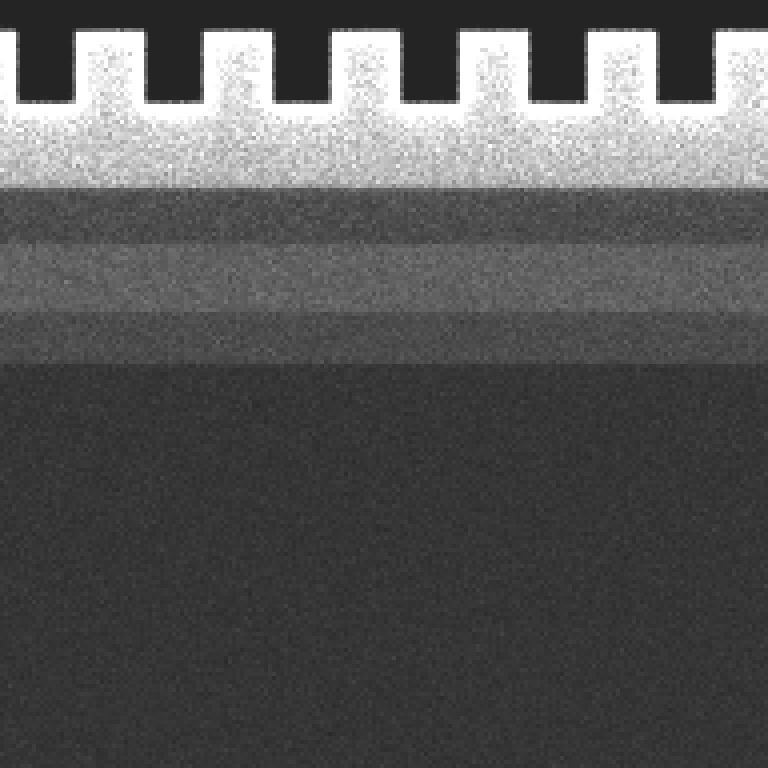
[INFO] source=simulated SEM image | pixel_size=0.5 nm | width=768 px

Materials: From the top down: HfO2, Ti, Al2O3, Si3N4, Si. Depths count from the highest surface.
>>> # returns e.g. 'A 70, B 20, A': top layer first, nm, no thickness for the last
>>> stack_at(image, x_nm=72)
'empty 36, HfO2 42, Ti 28, Al2O3 34, Si3N4 26, Si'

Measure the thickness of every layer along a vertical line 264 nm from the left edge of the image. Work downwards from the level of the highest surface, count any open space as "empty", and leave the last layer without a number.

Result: empty 36, HfO2 42, Ti 28, Al2O3 34, Si3N4 26, Si